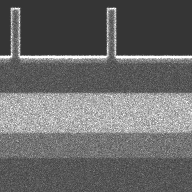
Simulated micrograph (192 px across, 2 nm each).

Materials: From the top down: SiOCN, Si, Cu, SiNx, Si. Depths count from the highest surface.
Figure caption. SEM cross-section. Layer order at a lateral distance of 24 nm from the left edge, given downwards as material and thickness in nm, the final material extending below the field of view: Si 170, Cu 80, SiNx 50, Si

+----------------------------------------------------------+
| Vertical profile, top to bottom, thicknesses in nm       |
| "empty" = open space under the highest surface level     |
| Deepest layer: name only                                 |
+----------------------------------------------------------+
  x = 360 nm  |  empty 96, SiOCN 14, Si 60, Cu 80, SiNx 50, Si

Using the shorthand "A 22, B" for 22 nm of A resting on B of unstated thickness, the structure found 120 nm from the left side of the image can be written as empty 96, SiOCN 14, Si 60, Cu 80, SiNx 50, Si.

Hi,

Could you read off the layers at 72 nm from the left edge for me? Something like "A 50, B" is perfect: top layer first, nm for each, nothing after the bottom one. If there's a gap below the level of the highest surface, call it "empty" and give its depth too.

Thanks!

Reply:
empty 96, SiOCN 14, Si 60, Cu 80, SiNx 50, Si